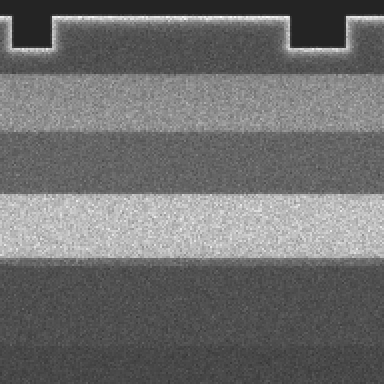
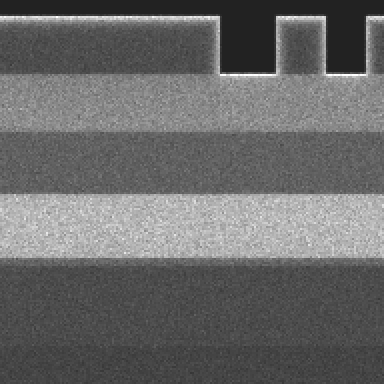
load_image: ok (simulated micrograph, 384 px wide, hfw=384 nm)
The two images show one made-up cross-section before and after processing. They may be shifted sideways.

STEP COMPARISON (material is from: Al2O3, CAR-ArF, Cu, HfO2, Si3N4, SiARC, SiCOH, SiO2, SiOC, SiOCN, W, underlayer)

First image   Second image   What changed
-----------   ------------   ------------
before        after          underlayer, removed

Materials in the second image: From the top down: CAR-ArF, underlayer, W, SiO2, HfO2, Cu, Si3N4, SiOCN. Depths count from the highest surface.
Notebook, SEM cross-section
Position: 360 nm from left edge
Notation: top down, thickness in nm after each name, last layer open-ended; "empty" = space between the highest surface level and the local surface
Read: empty 58, W 58, SiO2 62, HfO2 64, Cu 8, Si3N4 80, SiOCN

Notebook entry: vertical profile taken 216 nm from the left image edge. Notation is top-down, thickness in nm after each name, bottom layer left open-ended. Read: CAR-ArF 32, underlayer 26, W 58, SiO2 62, HfO2 64, Cu 8, Si3N4 80, SiOCN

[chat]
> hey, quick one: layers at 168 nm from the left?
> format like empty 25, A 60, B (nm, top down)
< CAR-ArF 32, underlayer 26, W 58, SiO2 62, HfO2 64, Cu 8, Si3N4 80, SiOCN